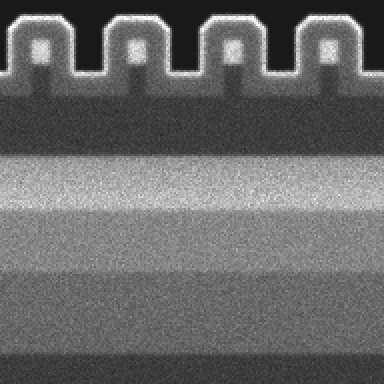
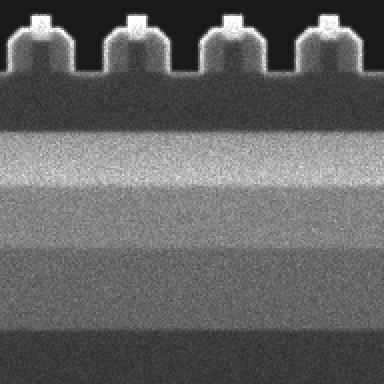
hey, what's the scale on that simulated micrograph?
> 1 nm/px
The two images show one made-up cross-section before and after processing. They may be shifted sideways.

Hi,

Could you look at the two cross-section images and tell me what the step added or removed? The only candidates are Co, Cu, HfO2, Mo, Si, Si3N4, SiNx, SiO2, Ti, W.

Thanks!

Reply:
removed SiNx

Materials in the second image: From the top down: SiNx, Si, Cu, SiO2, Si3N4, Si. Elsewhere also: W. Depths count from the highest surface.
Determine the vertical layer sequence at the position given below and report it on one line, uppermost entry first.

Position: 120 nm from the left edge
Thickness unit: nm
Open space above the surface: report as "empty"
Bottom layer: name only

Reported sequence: empty 12, SiNx 44, Si 60, Cu 54, SiO2 62, Si3N4 82, Si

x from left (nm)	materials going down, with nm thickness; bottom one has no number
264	empty 24, SiNx 32, Si 60, Cu 54, SiO2 62, Si3N4 82, Si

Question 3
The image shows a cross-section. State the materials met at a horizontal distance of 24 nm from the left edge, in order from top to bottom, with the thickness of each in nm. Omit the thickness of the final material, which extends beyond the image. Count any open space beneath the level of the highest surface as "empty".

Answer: empty 12, SiNx 44, Si 60, Cu 54, SiO2 62, Si3N4 82, Si